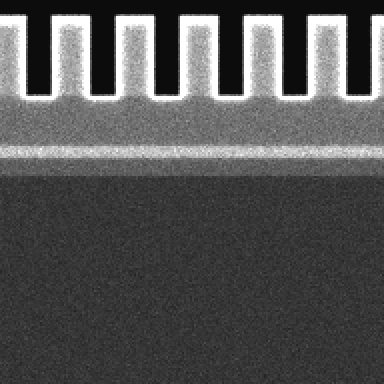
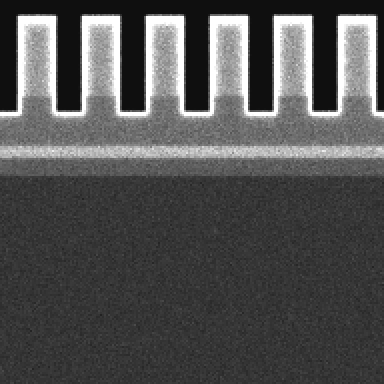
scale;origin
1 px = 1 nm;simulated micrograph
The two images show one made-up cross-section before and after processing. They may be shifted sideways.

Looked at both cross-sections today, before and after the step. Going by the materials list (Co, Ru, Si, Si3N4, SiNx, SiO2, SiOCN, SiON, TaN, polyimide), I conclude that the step removed Si3N4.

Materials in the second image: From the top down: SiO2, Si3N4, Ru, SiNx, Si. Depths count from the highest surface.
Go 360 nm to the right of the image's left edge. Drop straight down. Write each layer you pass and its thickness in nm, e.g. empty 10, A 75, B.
SiO2 80, Si3N4 50, Ru 12, SiNx 18, Si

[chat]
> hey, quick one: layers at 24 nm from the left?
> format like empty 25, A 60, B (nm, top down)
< SiO2 80, Si3N4 50, Ru 12, SiNx 18, Si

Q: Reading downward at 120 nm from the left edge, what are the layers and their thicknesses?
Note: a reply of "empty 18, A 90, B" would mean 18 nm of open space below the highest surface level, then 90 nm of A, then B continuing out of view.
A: empty 96, Si3N4 34, Ru 12, SiNx 18, Si